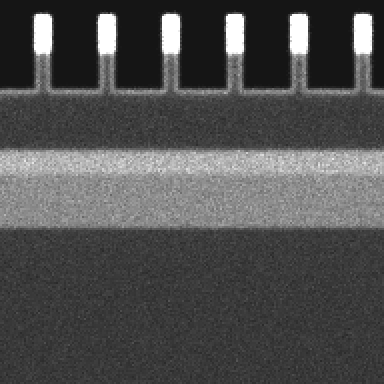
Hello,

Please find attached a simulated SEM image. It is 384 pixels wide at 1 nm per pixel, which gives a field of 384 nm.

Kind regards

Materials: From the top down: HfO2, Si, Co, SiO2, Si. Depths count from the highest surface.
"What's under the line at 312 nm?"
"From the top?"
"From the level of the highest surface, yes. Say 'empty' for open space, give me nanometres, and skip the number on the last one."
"empty 74, Si 60, Co 24, SiO2 54, Si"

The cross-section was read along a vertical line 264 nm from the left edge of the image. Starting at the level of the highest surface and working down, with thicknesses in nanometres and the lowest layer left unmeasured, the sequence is empty 74, Si 60, Co 24, SiO2 54, Si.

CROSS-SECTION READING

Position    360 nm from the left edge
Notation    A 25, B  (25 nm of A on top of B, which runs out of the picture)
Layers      HfO2 36, Si 98, Co 24, SiO2 54, Si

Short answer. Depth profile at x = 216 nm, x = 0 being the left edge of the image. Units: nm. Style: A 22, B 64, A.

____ empty 74, Si 60, Co 24, SiO2 54, Si